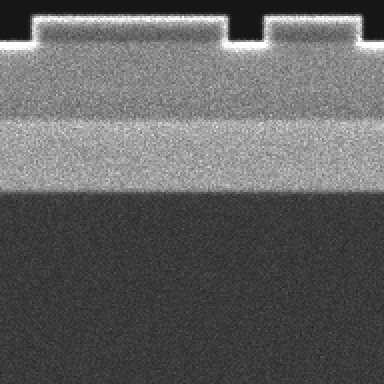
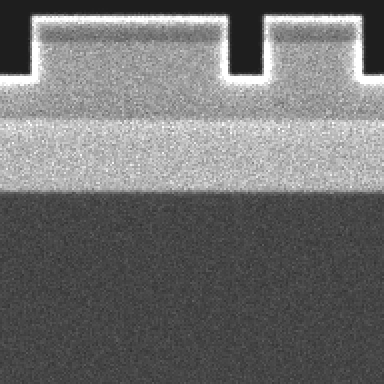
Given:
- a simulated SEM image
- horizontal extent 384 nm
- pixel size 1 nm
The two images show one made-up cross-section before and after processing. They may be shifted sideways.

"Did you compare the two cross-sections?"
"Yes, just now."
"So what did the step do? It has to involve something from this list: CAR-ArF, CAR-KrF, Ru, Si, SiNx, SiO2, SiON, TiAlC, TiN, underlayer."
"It removed SiO2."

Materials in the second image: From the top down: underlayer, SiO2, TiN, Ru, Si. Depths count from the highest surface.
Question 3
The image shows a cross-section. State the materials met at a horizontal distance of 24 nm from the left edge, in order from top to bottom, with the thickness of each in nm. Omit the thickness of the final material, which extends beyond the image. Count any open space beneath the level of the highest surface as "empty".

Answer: empty 60, SiO2 16, TiN 28, Ru 72, Si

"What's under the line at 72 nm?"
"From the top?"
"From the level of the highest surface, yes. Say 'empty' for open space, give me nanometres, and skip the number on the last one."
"underlayer 26, SiO2 50, TiN 28, Ru 72, Si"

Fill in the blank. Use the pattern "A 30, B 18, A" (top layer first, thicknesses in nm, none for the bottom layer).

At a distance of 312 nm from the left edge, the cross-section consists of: underlayer 26, SiO2 50, TiN 28, Ru 72, Si